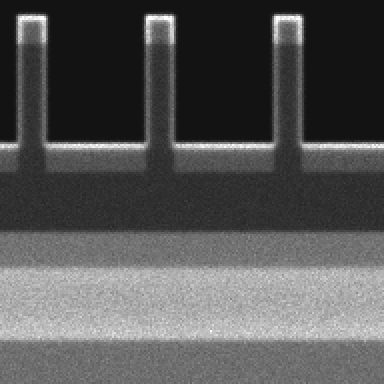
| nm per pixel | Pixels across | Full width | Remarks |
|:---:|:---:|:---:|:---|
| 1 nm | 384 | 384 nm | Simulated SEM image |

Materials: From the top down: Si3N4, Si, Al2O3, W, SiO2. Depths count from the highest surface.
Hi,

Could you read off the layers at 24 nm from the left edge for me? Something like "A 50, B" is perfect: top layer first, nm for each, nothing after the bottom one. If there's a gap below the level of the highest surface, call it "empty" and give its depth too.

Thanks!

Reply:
Si3N4 28, Si 188, Al2O3 36, W 72, SiO2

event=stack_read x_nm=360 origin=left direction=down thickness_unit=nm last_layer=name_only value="empty 128, Si3N4 28, Si 60, Al2O3 36, W 72, SiO2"